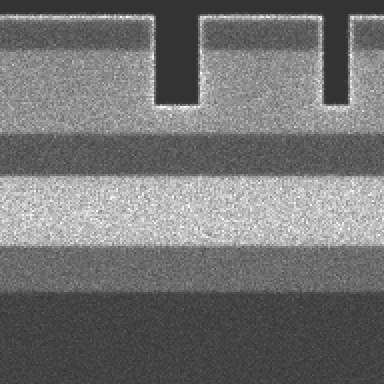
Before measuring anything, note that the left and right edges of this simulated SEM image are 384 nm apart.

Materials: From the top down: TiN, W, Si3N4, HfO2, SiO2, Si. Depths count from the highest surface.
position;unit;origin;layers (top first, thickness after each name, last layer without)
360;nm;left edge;TiN 34, W 84, Si3N4 42, HfO2 70, SiO2 46, Si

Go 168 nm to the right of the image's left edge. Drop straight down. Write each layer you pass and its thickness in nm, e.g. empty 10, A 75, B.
empty 90, W 28, Si3N4 42, HfO2 70, SiO2 46, Si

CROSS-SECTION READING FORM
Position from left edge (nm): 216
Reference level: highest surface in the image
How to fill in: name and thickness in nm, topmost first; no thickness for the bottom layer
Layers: TiN 34, W 84, Si3N4 42, HfO2 70, SiO2 46, Si